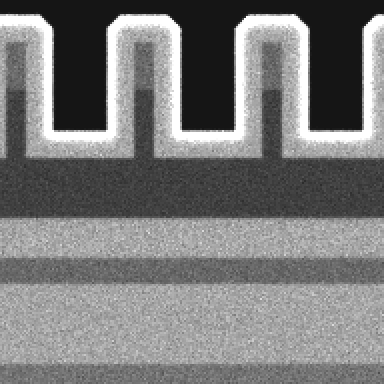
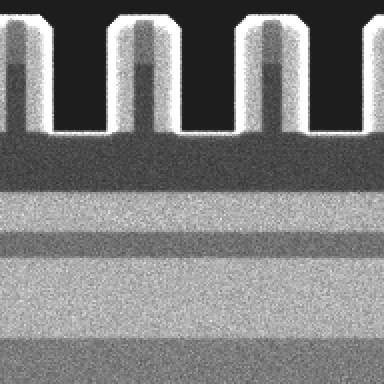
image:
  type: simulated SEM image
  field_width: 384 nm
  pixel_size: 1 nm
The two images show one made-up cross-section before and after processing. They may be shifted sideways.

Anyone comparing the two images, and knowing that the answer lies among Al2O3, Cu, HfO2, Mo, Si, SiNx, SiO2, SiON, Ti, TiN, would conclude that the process removed SiO2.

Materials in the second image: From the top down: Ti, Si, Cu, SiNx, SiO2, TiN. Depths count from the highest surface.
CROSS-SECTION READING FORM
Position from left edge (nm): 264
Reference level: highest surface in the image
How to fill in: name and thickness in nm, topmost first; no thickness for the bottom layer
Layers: Ti 48, Si 128, Cu 40, SiNx 26, SiO2 80, TiN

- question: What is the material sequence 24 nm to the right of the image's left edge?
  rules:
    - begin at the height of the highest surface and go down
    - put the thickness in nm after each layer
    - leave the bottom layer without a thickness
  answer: Ti 48, Si 128, Cu 40, SiNx 26, SiO2 80, TiN